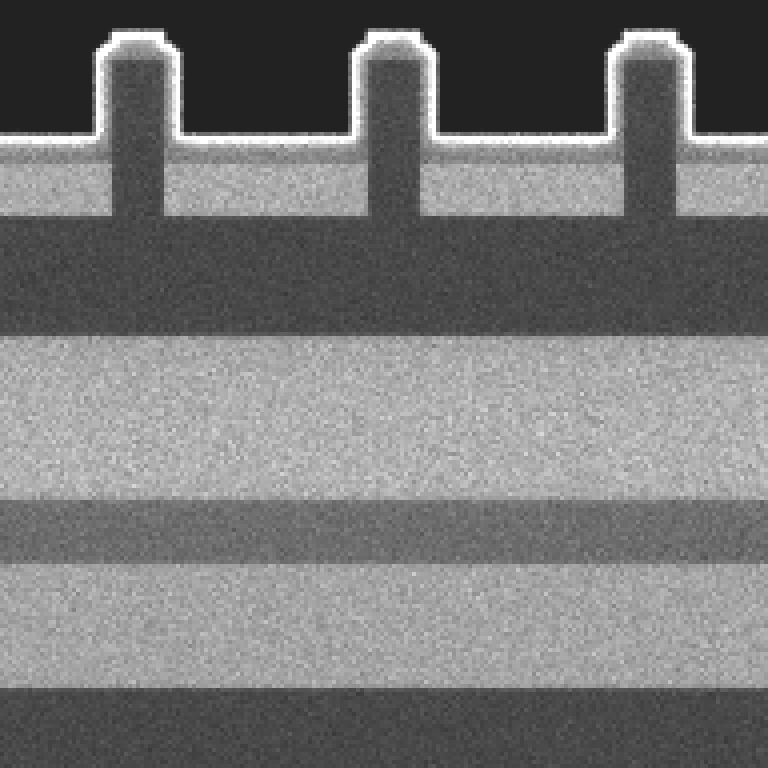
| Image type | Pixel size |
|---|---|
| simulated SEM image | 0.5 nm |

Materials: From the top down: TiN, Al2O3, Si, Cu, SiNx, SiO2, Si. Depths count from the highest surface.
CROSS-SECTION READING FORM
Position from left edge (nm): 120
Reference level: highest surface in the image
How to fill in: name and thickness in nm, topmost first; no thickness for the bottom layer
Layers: empty 52, TiN 14, Al2O3 26, Si 60, Cu 82, SiNx 32, SiO2 62, Si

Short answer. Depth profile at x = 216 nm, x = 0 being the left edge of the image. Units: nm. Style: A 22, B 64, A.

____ empty 10, TiN 56, Al2O3 26, Si 60, Cu 82, SiNx 32, SiO2 62, Si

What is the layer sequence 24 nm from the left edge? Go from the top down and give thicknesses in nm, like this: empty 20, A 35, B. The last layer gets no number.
empty 52, TiN 14, Al2O3 26, Si 60, Cu 82, SiNx 32, SiO2 62, Si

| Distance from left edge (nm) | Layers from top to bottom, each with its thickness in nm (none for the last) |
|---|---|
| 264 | empty 52, TiN 14, Al2O3 26, Si 60, Cu 82, SiNx 32, SiO2 62, Si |